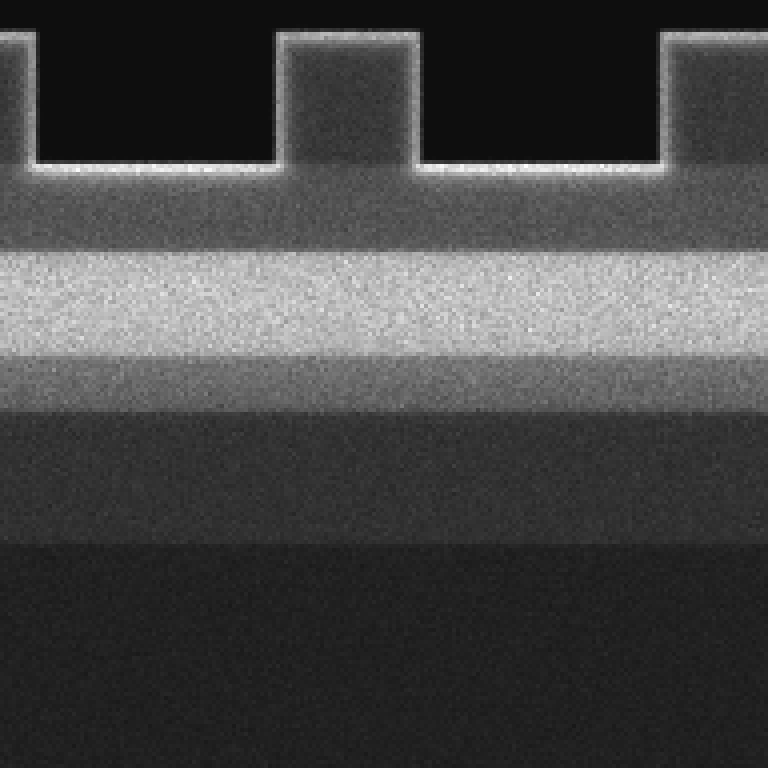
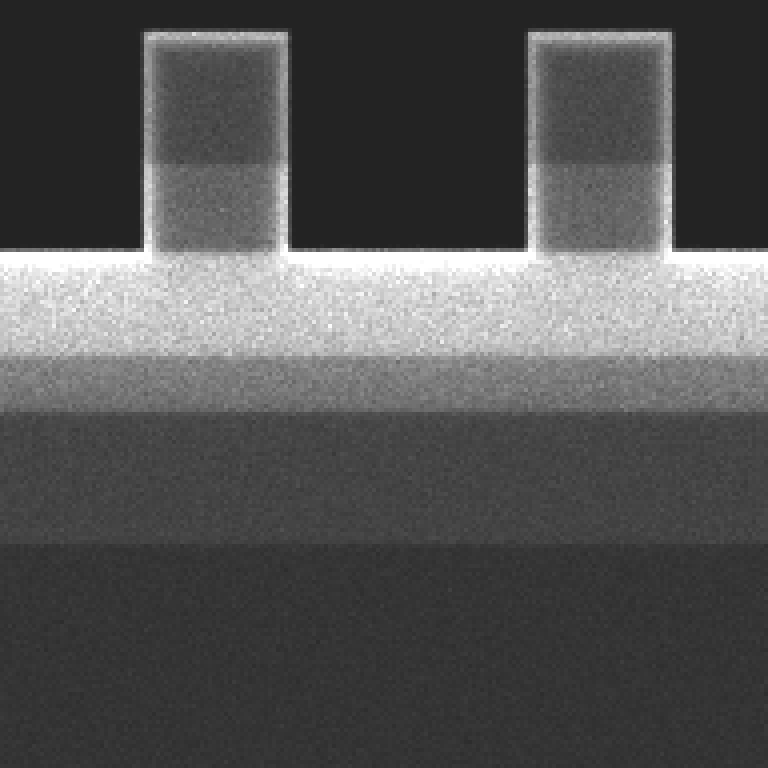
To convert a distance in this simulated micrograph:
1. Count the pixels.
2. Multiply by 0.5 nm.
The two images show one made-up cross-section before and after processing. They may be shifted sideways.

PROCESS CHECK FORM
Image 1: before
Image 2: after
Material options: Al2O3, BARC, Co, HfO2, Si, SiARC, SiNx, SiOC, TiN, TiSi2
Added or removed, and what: removed, Al2O3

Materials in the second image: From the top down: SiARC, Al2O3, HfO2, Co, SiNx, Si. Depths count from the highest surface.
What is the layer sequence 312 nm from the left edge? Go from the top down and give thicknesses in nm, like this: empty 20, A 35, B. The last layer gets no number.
SiARC 66, Al2O3 44, HfO2 52, Co 28, SiNx 66, Si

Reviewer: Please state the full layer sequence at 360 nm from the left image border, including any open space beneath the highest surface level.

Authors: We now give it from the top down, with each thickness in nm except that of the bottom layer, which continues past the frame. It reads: empty 110, HfO2 52, Co 28, SiNx 66, Si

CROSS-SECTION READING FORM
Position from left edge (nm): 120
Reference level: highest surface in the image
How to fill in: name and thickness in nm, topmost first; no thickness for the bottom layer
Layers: SiARC 66, Al2O3 44, HfO2 52, Co 28, SiNx 66, Si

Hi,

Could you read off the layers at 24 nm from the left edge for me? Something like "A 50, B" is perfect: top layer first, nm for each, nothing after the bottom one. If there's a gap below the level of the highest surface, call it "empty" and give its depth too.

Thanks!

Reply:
empty 110, HfO2 52, Co 28, SiNx 66, Si